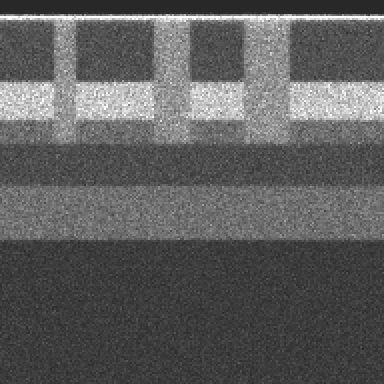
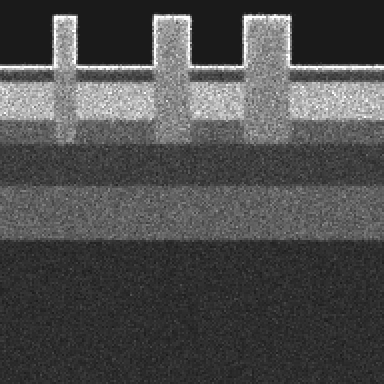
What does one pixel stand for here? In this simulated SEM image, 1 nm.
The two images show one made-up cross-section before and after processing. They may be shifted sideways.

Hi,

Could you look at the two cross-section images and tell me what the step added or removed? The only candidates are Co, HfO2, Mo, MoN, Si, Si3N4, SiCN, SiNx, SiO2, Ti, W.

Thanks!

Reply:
removed SiNx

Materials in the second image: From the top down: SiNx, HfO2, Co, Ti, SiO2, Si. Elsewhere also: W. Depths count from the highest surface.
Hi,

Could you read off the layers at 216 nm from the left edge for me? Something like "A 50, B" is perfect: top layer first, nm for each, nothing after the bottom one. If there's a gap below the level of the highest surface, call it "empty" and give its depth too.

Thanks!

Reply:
empty 50, SiNx 16, HfO2 38, Co 24, Ti 42, SiO2 54, Si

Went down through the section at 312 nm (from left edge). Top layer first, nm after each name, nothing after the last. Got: empty 50, SiNx 16, HfO2 38, Co 24, Ti 42, SiO2 54, Si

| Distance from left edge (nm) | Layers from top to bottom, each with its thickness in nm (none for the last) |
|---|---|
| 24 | empty 50, SiNx 16, HfO2 38, Co 24, Ti 42, SiO2 54, Si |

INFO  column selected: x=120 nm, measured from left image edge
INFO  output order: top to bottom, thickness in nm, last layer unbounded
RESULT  empty 50, SiNx 16, HfO2 38, Co 24, Ti 42, SiO2 54, Si